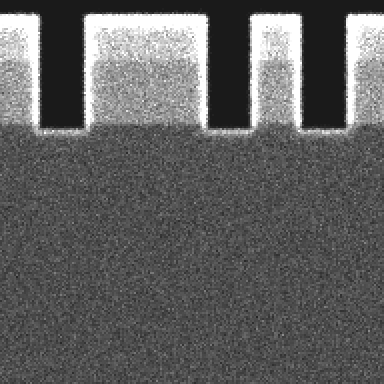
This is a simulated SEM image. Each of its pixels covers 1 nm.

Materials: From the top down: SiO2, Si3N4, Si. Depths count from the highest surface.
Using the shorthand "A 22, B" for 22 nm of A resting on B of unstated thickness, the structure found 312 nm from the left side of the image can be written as empty 114, Si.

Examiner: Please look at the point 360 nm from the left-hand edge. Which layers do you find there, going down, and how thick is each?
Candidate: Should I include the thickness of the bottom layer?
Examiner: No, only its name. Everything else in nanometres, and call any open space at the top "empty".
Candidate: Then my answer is SiO2 44, Si3N4 64, Si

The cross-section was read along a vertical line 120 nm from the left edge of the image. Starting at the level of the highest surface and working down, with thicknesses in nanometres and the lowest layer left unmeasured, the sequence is SiO2 44, Si3N4 64, Si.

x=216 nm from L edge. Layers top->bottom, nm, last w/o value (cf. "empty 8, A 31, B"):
empty 114, Si